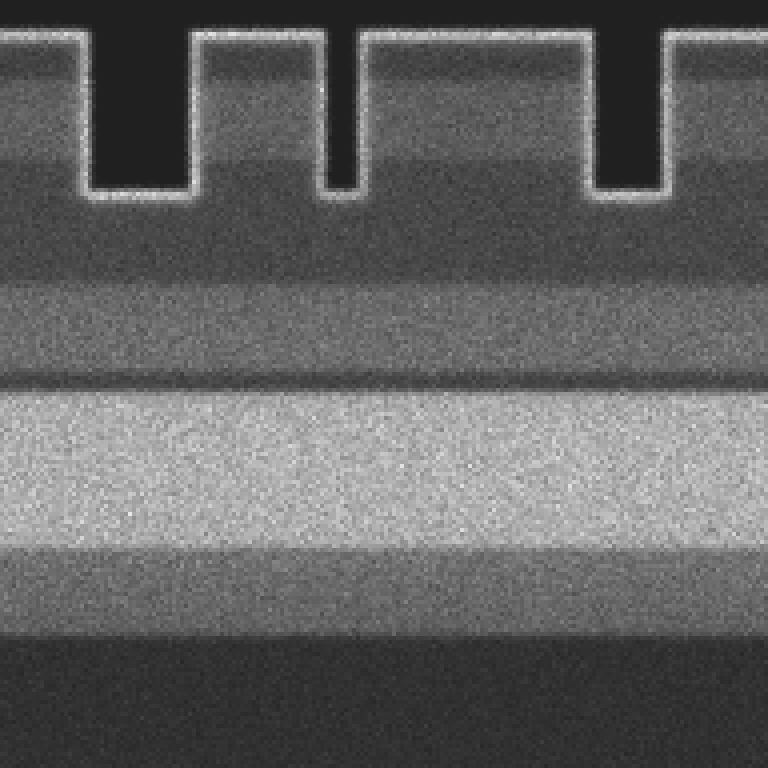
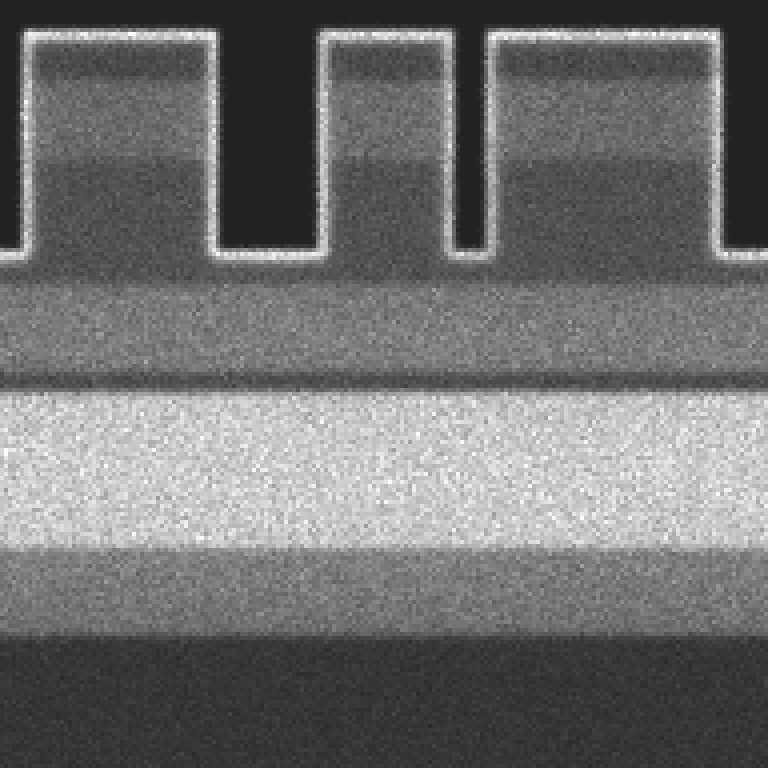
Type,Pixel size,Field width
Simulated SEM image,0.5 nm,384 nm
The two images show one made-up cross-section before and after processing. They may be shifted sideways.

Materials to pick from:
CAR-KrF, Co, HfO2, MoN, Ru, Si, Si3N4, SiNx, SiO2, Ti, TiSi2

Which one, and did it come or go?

Si3N4 - removed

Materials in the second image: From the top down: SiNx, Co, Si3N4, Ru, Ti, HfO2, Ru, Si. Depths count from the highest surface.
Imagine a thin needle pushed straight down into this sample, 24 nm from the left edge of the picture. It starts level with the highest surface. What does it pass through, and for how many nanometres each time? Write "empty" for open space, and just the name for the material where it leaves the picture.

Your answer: SiNx 24, Co 40, Si3N4 62, Ru 44, Ti 10, HfO2 78, Ru 44, Si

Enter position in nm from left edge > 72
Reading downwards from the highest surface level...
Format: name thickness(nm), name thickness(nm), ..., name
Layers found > SiNx 24, Co 40, Si3N4 62, Ru 44, Ti 10, HfO2 78, Ru 44, Si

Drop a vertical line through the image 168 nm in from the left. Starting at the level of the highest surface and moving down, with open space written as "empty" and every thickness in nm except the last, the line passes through SiNx 24, Co 40, Si3N4 62, Ru 44, Ti 10, HfO2 78, Ru 44, Si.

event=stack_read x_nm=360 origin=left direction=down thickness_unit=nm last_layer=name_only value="empty 110, Si3N4 16, Ru 44, Ti 10, HfO2 78, Ru 44, Si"